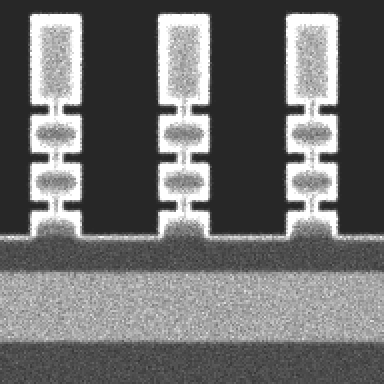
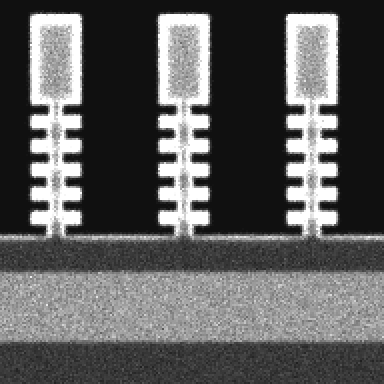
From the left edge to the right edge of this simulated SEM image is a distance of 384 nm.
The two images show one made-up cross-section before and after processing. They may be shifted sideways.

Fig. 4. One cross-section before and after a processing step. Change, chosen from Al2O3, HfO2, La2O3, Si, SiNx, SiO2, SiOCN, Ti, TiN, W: TiN removed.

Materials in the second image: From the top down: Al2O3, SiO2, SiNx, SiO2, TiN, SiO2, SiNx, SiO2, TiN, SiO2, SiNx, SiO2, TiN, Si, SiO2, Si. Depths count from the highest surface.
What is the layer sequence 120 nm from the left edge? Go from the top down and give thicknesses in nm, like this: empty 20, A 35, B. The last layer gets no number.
empty 220, Si 36, SiO2 70, Si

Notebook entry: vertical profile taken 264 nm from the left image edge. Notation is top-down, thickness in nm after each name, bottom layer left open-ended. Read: empty 220, Si 36, SiO2 70, Si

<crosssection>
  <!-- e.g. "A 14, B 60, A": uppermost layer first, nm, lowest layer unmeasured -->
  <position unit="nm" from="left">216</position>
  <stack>empty 220, Si 36, SiO2 70, Si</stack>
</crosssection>